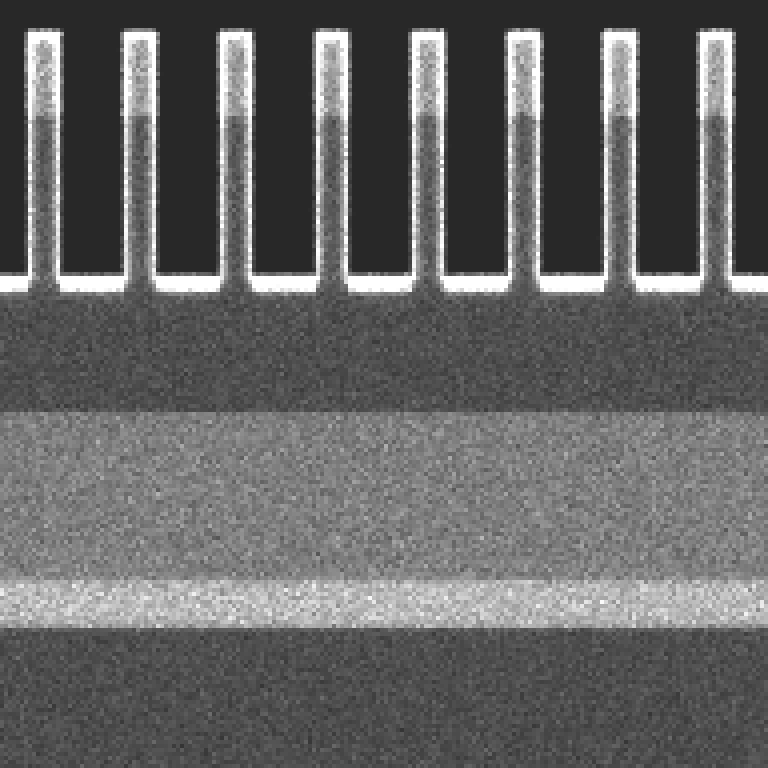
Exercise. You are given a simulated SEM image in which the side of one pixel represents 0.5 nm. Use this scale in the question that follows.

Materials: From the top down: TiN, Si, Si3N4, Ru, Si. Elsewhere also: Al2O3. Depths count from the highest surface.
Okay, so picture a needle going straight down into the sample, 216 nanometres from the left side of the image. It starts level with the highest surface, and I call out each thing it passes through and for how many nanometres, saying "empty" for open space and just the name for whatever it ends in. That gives TiN 42, Si 148, Si3N4 84, Ru 24, Si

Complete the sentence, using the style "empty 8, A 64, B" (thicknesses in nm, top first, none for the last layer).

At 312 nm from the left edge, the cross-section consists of TiN 42, Si 148, Si3N4 84, Ru 24, Si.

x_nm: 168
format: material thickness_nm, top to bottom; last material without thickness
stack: TiN 42, Si 148, Si3N4 84, Ru 24, Si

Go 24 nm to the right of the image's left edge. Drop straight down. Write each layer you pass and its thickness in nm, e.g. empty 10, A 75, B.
TiN 42, Si 148, Si3N4 84, Ru 24, Si